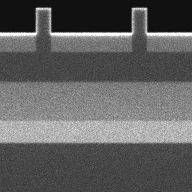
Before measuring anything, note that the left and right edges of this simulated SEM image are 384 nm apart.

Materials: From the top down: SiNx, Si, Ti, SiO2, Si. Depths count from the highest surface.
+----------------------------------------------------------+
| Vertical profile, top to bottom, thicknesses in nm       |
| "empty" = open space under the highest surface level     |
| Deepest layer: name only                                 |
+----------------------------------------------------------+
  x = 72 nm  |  Si 148, Ti 78, SiO2 44, Si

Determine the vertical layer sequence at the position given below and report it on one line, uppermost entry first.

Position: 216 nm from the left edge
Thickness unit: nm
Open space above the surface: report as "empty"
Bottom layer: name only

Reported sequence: empty 50, SiNx 38, Si 60, Ti 78, SiO2 44, Si